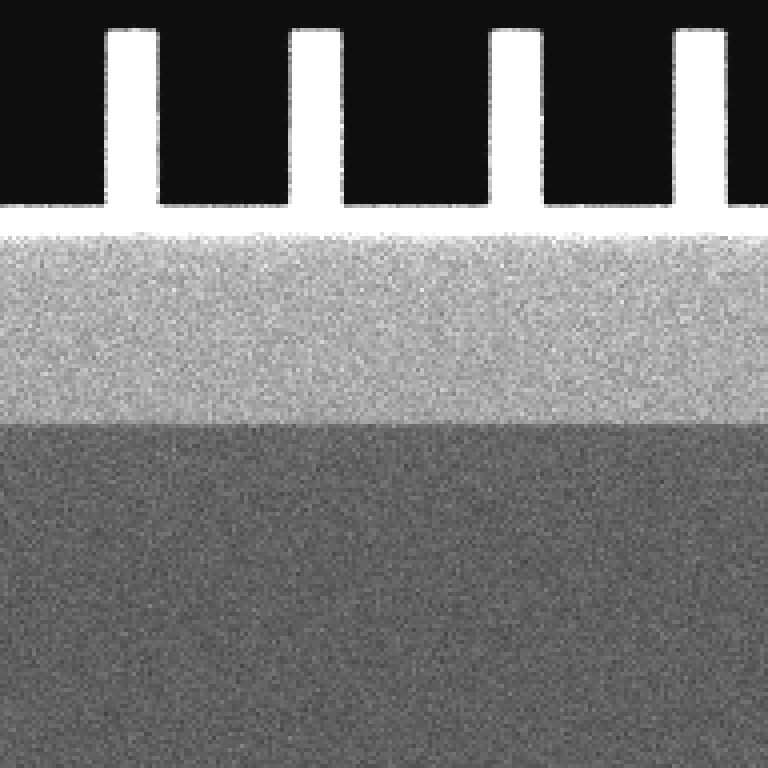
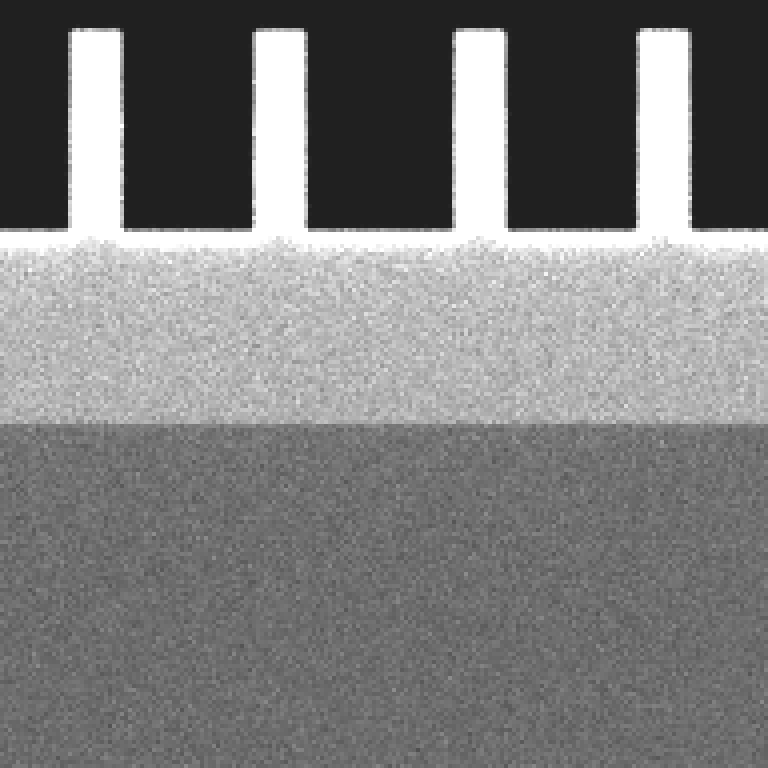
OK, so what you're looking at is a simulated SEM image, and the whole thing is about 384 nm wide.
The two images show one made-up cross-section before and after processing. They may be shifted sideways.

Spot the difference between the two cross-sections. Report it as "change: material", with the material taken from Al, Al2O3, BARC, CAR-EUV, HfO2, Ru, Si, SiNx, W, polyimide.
removed: Ru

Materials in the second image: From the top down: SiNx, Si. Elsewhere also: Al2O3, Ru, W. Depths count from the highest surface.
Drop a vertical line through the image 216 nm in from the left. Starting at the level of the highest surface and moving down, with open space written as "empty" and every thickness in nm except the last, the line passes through empty 100, SiNx 96, Si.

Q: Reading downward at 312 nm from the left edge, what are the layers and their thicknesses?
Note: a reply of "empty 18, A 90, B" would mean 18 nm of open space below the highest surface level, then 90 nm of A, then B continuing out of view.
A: empty 100, SiNx 96, Si